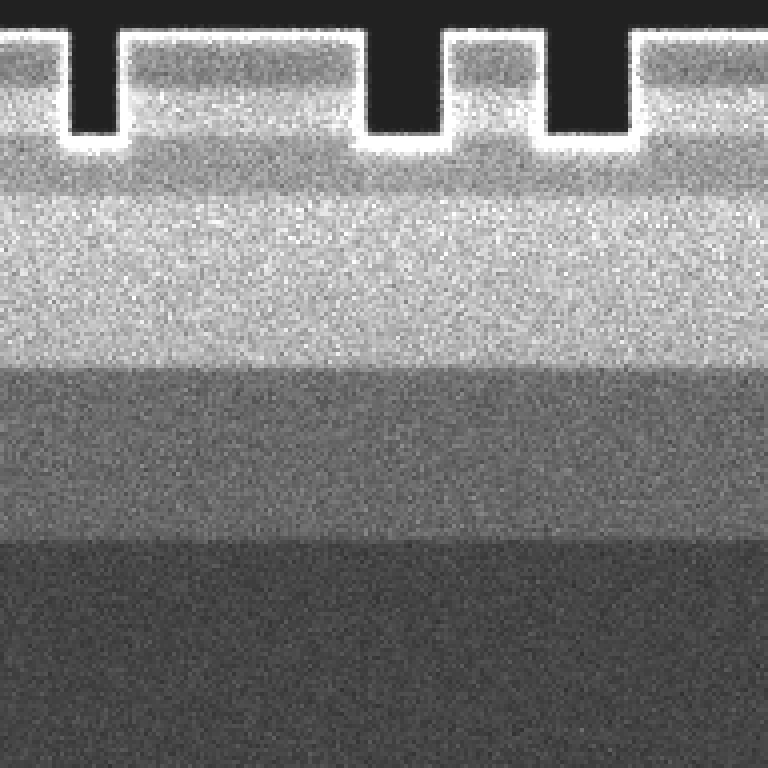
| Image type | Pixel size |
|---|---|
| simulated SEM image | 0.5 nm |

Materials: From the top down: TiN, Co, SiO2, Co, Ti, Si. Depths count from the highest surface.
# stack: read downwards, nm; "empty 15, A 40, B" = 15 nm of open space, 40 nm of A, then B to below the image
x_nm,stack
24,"TiN 28, Co 24, SiO2 30, Co 86, Ti 86, Si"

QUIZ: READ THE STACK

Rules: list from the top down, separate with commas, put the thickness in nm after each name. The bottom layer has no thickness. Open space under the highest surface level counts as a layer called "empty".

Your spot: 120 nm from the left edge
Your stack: TiN 28, Co 24, SiO2 30, Co 86, Ti 86, Si